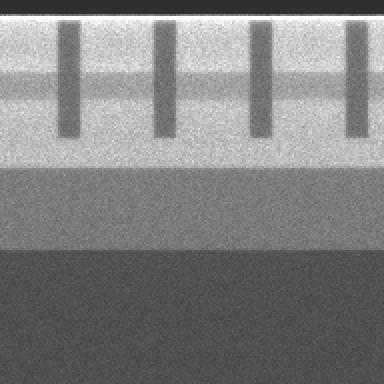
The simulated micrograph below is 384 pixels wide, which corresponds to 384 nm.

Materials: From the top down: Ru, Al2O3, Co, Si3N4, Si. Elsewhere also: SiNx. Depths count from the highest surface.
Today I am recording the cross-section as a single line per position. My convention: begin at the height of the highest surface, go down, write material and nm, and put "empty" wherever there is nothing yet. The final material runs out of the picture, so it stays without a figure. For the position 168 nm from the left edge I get SiNx 122, Co 30, Si3N4 82, Si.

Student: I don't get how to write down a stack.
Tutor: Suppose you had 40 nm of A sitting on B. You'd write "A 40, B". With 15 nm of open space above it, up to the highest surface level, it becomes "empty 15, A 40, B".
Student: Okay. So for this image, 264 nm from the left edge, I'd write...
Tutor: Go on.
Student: SiNx 122, Co 30, Si3N4 82, Si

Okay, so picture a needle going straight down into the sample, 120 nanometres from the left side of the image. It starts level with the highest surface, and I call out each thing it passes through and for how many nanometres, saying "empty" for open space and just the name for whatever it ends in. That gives Ru 56, Al2O3 28, Co 68, Si3N4 82, Si